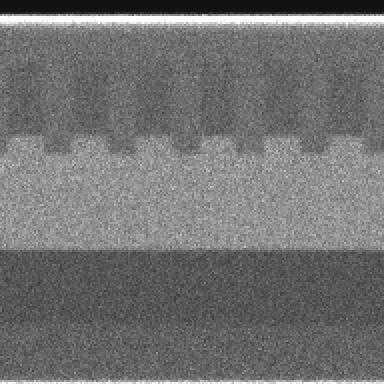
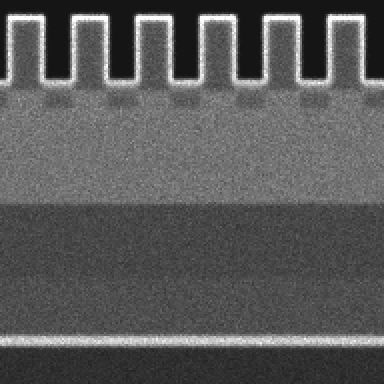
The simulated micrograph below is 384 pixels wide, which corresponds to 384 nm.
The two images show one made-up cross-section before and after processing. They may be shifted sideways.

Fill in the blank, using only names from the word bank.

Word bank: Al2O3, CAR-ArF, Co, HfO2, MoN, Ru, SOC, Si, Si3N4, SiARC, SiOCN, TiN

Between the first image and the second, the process removed SOC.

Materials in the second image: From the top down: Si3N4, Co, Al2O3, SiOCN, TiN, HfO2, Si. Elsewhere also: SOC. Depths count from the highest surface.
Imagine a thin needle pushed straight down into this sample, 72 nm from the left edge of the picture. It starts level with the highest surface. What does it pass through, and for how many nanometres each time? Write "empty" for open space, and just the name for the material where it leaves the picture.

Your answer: Si3N4 74, Co 38, Al2O3 76, SiOCN 74, TiN 58, HfO2 10, Si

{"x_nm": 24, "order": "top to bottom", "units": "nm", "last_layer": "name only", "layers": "Si3N4 74, Co 38, Al2O3 76, SiOCN 74, TiN 58, HfO2 10, Si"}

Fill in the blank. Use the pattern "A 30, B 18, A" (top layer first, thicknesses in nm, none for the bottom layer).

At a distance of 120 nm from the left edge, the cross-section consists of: empty 64, SOC 28, Co 20, Al2O3 76, SiOCN 74, TiN 58, HfO2 10, Si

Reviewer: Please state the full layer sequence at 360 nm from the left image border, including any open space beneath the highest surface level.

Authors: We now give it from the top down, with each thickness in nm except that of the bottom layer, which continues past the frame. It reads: Si3N4 74, Co 38, Al2O3 76, SiOCN 74, TiN 58, HfO2 10, Si